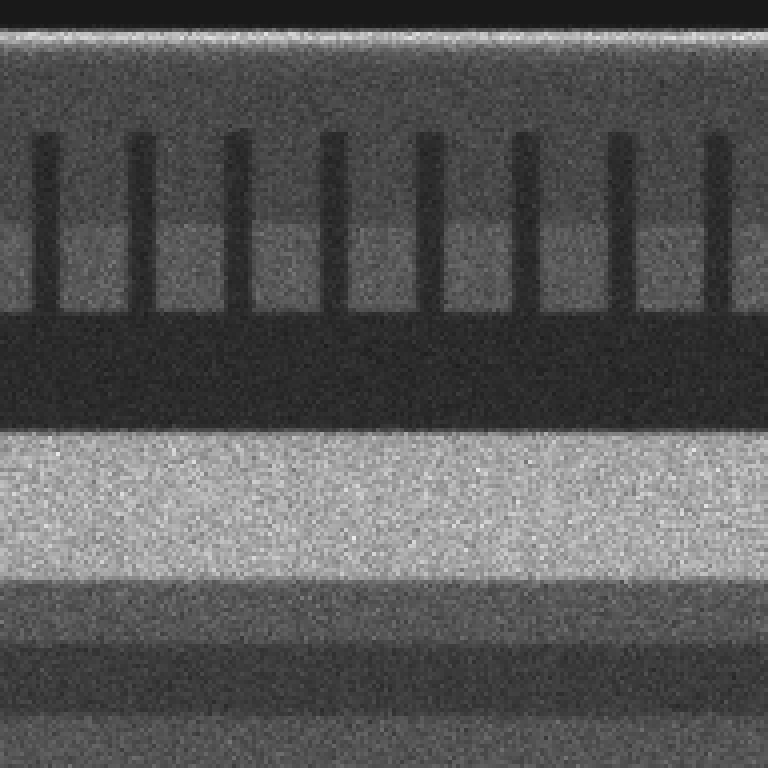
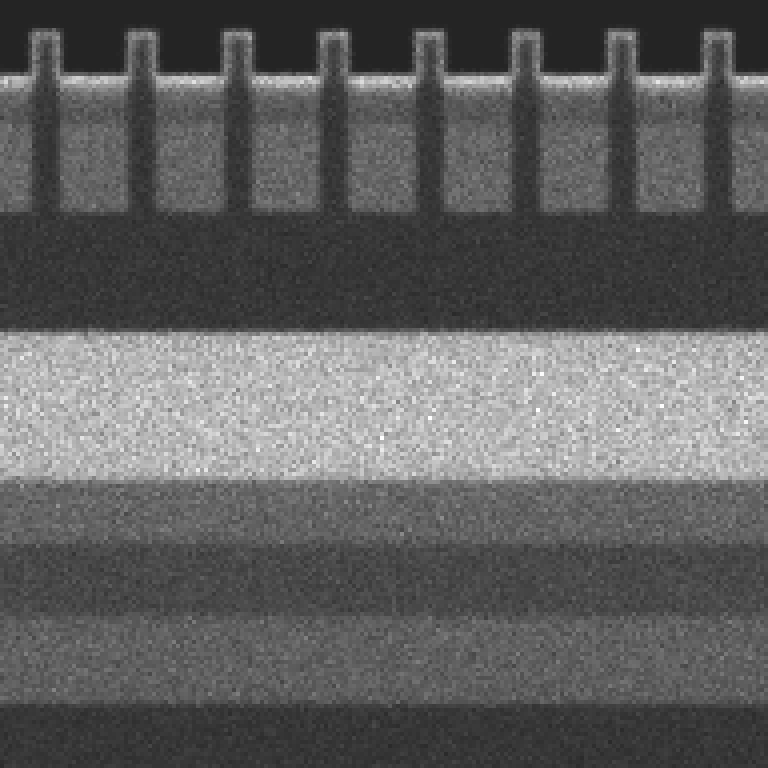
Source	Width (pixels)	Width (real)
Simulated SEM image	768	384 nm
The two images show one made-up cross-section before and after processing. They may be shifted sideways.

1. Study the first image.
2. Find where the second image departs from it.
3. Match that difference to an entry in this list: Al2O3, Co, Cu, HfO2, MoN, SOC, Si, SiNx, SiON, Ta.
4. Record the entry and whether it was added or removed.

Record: SOC / removed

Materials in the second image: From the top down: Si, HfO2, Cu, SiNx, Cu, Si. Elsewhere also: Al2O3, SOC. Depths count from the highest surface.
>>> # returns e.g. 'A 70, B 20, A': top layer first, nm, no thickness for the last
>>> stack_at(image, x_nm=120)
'Si 150, HfO2 74, Cu 32, SiNx 36, Cu 44, Si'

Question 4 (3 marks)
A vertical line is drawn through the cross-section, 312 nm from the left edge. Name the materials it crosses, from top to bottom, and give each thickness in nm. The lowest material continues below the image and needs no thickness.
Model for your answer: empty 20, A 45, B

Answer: Si 150, HfO2 74, Cu 32, SiNx 36, Cu 44, Si